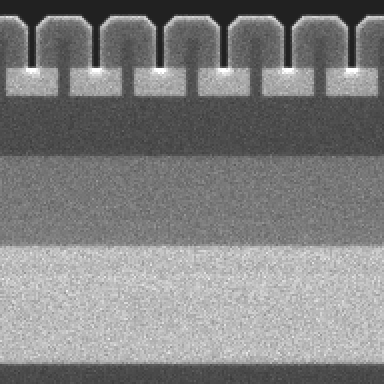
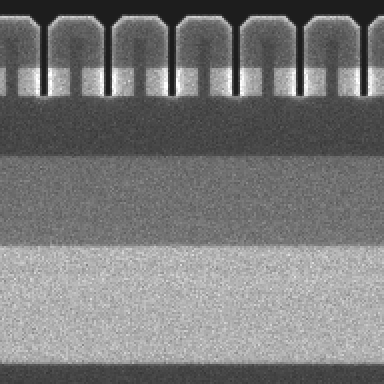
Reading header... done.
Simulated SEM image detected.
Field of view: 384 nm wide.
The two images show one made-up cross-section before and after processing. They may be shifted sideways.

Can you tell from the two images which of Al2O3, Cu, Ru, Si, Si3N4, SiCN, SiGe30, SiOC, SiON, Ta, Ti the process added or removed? Yes, it removed Al2O3.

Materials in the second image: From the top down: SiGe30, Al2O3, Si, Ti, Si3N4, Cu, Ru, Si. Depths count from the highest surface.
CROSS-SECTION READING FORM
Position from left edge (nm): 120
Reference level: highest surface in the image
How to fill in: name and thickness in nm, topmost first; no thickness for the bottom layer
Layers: empty 2, SiGe30 50, Al2O3 28, Si 60, Ti 64, Si3N4 26, Cu 28, Ru 90, Si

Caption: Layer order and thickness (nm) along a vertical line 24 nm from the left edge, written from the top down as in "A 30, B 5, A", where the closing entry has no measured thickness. SiGe30 52, Al2O3 28, Si 60, Ti 64, Si3N4 26, Cu 28, Ru 90, Si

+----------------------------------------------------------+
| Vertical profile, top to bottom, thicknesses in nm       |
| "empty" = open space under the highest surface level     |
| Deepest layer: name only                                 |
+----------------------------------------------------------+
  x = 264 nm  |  SiGe30 22, Si 118, Ti 64, Si3N4 26, Cu 28, Ru 90, Si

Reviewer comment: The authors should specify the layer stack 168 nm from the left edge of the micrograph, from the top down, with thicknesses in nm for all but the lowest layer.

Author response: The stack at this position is empty 80, Si 60, Ti 64, Si3N4 26, Cu 28, Ru 90, Si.